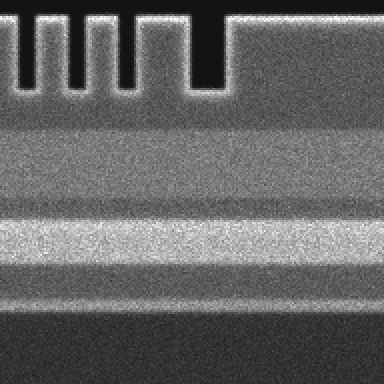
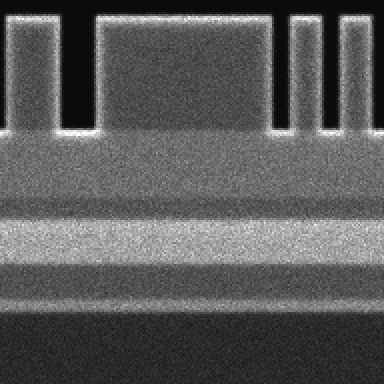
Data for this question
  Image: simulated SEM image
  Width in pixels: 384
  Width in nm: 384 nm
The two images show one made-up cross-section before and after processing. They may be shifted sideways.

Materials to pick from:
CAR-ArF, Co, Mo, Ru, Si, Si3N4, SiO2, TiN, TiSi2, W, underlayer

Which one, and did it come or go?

underlayer - removed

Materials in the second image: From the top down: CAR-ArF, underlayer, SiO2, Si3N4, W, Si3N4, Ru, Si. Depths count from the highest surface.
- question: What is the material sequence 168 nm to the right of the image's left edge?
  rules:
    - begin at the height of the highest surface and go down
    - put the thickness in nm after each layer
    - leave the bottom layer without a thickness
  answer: CAR-ArF 74, underlayer 40, SiO2 68, Si3N4 22, W 44, Si3N4 36, Ru 12, Si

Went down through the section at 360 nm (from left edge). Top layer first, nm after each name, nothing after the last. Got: CAR-ArF 74, underlayer 40, SiO2 68, Si3N4 22, W 44, Si3N4 36, Ru 12, Si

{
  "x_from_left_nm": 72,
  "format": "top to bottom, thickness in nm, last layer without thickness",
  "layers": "empty 114, SiO2 68, Si3N4 22, W 44, Si3N4 36, Ru 12, Si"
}